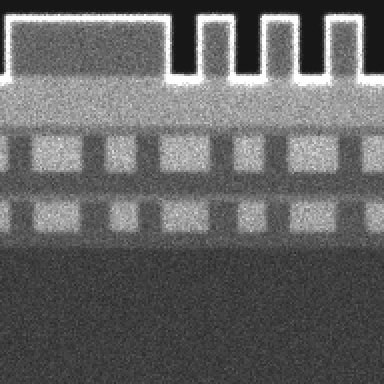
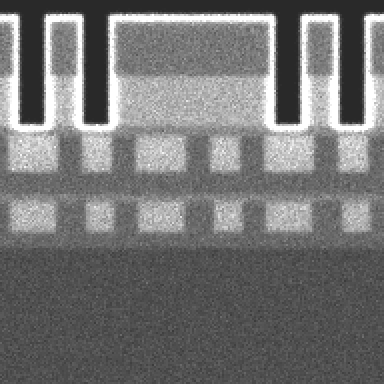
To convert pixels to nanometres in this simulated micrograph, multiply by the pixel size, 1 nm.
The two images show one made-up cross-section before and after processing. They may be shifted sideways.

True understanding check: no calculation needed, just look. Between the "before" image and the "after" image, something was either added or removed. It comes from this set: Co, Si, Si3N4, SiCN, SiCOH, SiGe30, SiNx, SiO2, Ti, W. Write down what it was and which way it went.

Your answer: SiO2 (removed)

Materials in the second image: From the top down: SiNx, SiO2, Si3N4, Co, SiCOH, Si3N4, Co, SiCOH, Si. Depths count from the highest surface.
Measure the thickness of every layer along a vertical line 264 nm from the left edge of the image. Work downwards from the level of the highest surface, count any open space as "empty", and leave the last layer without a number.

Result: SiNx 60, SiO2 50, Si3N4 10, Co 36, SiCOH 22, Si3N4 8, SiCOH 46, Si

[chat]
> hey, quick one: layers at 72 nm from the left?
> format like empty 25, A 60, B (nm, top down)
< SiNx 60, SiO2 50, Si3N4 10, SiCOH 58, Si3N4 8, SiCOH 46, Si